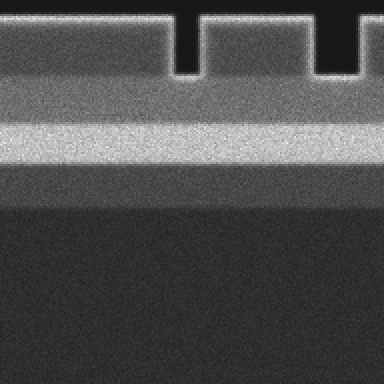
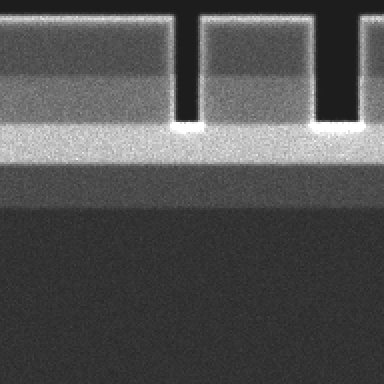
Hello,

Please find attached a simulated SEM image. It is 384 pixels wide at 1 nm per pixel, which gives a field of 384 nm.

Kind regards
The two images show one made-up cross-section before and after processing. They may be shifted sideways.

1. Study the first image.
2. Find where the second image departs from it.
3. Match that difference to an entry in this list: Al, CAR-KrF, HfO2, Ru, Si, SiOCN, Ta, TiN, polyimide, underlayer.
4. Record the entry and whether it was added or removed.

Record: Ru / removed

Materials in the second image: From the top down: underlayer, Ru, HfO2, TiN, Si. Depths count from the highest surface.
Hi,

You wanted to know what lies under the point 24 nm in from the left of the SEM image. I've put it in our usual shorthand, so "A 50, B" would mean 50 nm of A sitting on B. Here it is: underlayer 60, Ru 48, HfO2 40, TiN 44, Si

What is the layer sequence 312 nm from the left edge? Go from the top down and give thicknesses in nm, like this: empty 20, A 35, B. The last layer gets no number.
underlayer 60, Ru 48, HfO2 40, TiN 44, Si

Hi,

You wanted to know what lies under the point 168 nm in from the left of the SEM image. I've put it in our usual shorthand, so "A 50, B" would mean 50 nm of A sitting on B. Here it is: underlayer 60, Ru 48, HfO2 40, TiN 44, Si